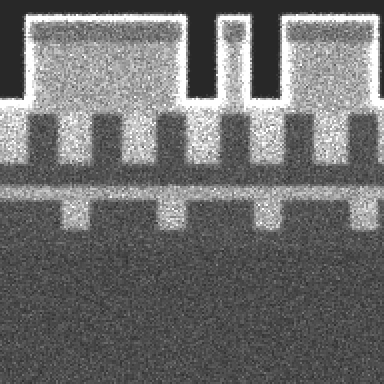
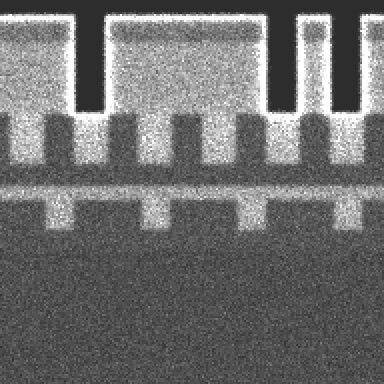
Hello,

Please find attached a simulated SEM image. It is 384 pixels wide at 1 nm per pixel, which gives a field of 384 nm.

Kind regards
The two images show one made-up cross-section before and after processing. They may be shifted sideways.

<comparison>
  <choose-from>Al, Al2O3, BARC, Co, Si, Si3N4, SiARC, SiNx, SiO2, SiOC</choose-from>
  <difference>Al2O3 removed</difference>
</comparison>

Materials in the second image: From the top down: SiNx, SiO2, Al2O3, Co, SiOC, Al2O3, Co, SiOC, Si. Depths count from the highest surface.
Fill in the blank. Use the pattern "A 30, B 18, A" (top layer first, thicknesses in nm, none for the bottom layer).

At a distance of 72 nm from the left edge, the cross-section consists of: SiNx 26, SiO2 58, Al2O3 14, SiOC 72, Al2O3 14, Co 30, SiOC 20, Si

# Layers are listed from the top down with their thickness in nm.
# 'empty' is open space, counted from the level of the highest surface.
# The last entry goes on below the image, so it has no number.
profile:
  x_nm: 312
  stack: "SiNx 26, SiO2 58, Al2O3 14, SiOC 72, Al2O3 14, SiOC 50, Si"